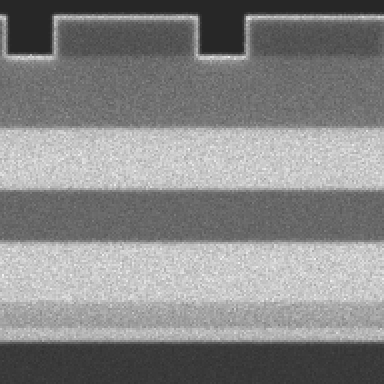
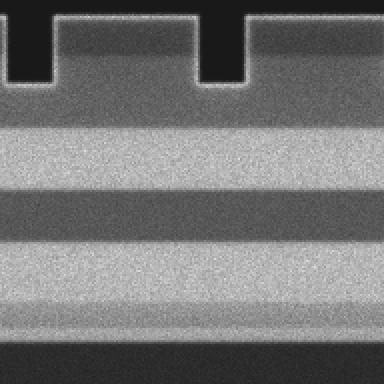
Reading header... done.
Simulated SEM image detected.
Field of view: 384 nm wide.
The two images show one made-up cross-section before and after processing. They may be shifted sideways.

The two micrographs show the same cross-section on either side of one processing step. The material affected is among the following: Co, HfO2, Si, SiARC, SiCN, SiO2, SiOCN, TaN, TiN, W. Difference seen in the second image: Co removed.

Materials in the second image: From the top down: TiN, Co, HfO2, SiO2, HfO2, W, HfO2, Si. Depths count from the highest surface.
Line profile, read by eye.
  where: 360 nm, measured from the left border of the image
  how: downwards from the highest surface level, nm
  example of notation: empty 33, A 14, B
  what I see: TiN 40, Co 72, HfO2 62, SiO2 52, HfO2 60, W 26, HfO2 14, Si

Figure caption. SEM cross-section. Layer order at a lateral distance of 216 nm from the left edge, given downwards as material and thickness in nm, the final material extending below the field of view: empty 68, Co 44, HfO2 62, SiO2 52, HfO2 60, W 26, HfO2 14, Si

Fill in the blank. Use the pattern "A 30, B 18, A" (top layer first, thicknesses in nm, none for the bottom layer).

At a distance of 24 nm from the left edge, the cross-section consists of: empty 68, Co 44, HfO2 62, SiO2 52, HfO2 60, W 26, HfO2 14, Si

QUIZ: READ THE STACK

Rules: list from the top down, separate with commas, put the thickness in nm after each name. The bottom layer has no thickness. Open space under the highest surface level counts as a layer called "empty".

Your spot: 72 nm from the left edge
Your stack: TiN 40, Co 72, HfO2 62, SiO2 52, HfO2 60, W 26, HfO2 14, Si